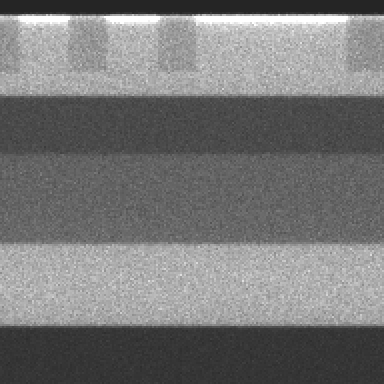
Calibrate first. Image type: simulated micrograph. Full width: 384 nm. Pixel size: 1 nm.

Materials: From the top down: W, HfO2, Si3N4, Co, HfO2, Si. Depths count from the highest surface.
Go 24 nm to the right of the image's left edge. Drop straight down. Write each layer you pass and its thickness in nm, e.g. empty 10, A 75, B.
HfO2 80, Si3N4 58, Co 90, HfO2 82, Si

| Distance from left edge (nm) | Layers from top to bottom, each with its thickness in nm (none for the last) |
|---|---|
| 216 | HfO2 80, Si3N4 58, Co 90, HfO2 82, Si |